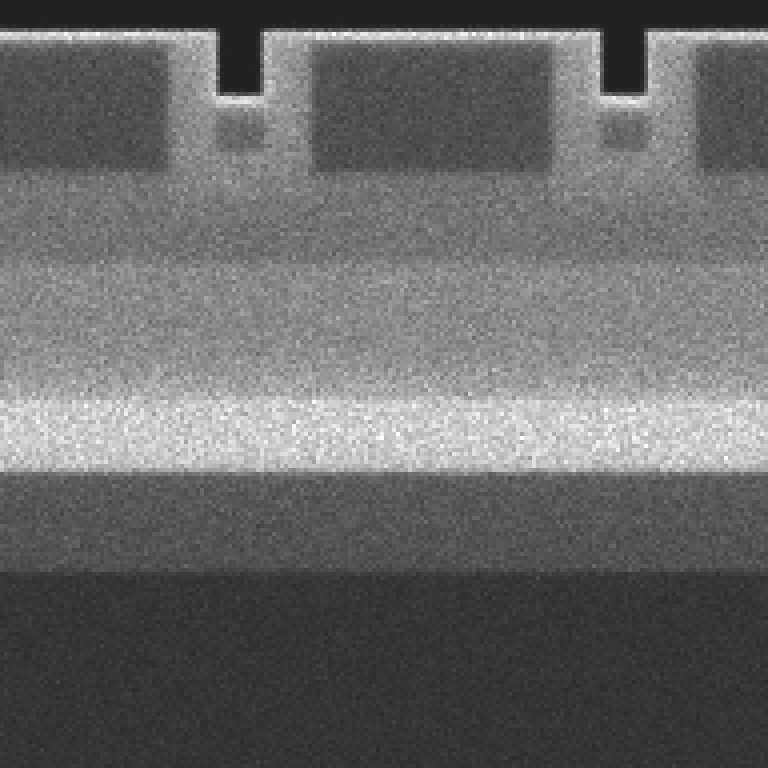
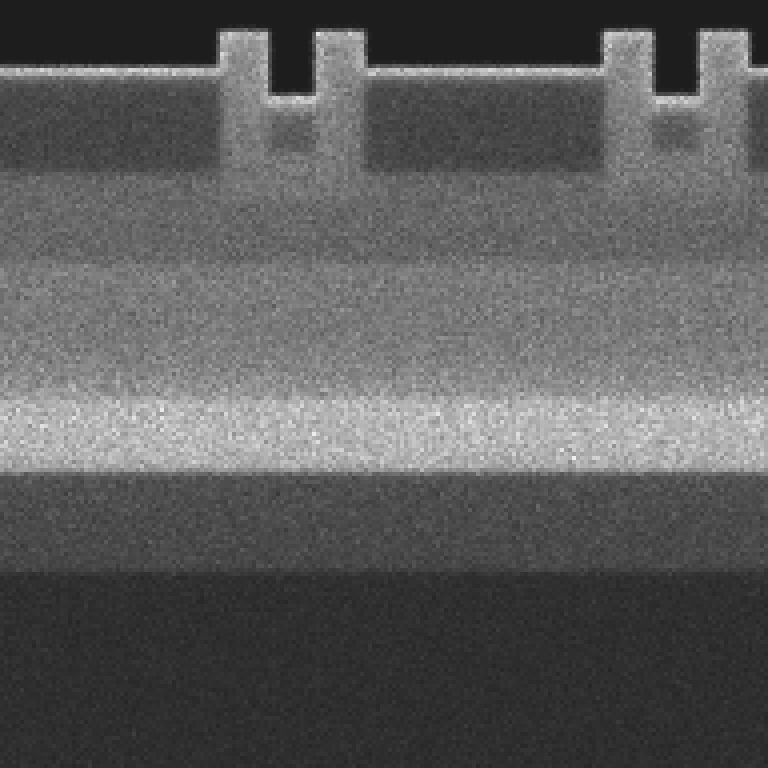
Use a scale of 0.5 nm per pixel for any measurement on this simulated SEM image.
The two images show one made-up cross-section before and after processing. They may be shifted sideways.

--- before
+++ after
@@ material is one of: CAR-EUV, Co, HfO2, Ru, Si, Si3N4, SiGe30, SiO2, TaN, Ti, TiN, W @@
Si3N4 removed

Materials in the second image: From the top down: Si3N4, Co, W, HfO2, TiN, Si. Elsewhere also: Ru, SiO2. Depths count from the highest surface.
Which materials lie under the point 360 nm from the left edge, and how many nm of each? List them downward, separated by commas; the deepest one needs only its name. Ru 84, Co 32, W 68, HfO2 36, TiN 50, Si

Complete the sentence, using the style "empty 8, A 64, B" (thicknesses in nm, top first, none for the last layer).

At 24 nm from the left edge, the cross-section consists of empty 18, Si3N4 52, Co 46, W 68, HfO2 36, TiN 50, Si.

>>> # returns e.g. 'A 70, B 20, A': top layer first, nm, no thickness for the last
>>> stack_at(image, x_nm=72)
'empty 18, Si3N4 52, Co 46, W 68, HfO2 36, TiN 50, Si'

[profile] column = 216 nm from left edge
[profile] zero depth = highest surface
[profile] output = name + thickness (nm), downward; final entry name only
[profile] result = empty 18, Si3N4 52, Co 46, W 68, HfO2 36, TiN 50, Si